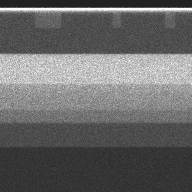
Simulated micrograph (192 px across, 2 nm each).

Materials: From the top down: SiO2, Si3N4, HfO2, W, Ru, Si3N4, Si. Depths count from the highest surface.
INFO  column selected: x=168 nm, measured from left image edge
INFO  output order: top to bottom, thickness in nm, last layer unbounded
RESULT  SiO2 6, Si3N4 86, HfO2 60, W 52, Ru 26, Si3N4 48, Si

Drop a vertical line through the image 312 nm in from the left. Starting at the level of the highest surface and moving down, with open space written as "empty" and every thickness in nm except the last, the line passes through SiO2 6, Si3N4 86, HfO2 60, W 52, Ru 26, Si3N4 48, Si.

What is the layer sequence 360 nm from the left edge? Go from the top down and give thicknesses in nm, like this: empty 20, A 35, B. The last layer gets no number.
SiO2 6, Si3N4 86, HfO2 60, W 52, Ru 26, Si3N4 48, Si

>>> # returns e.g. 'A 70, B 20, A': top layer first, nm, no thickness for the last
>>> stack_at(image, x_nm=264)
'SiO2 6, Si3N4 86, HfO2 60, W 52, Ru 26, Si3N4 48, Si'